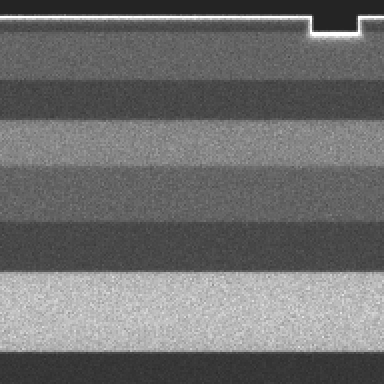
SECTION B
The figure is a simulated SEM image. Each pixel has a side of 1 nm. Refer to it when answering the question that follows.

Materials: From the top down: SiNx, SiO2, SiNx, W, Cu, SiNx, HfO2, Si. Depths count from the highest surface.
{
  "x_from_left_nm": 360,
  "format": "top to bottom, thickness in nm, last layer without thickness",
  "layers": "SiNx 16, SiO2 48, SiNx 40, W 46, Cu 56, SiNx 50, HfO2 80, Si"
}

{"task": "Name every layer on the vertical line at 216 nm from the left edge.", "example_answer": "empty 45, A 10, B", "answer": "SiNx 16, SiO2 48, SiNx 40, W 46, Cu 56, SiNx 50, HfO2 80, Si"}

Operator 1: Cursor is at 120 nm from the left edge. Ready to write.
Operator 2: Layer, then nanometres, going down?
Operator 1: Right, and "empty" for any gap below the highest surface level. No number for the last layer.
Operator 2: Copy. SiNx 16, SiO2 48, SiNx 40, W 46, Cu 56, SiNx 50, HfO2 80, Si